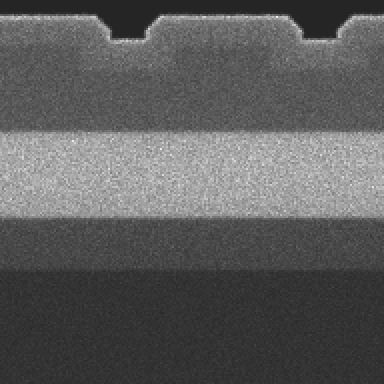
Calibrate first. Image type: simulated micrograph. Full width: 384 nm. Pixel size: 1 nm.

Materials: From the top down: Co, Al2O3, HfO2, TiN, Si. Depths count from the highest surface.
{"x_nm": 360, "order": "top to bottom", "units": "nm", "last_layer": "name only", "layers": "Co 54, Al2O3 62, HfO2 86, TiN 52, Si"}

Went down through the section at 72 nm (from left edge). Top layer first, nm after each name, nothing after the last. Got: Co 30, Al2O3 86, HfO2 86, TiN 52, Si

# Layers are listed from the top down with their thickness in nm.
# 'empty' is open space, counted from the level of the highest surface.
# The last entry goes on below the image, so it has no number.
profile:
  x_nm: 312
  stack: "empty 24, Co 30, Al2O3 62, HfO2 86, TiN 52, Si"